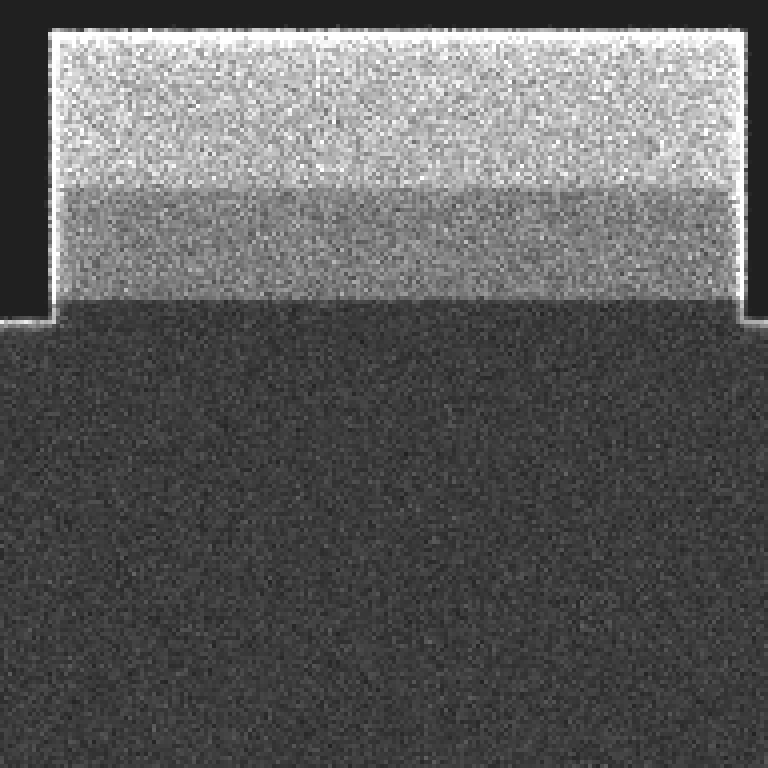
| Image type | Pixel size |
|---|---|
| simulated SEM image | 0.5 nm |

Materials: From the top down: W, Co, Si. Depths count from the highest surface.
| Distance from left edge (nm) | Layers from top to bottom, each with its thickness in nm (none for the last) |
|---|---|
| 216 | W 78, Co 56, Si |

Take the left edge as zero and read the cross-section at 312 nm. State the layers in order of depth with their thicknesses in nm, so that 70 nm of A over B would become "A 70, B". W 78, Co 56, Si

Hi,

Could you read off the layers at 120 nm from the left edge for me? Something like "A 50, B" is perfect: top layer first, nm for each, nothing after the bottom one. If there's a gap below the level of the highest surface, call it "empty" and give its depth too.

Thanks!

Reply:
W 78, Co 56, Si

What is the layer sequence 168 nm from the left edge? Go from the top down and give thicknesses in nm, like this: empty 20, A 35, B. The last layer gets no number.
W 78, Co 56, Si